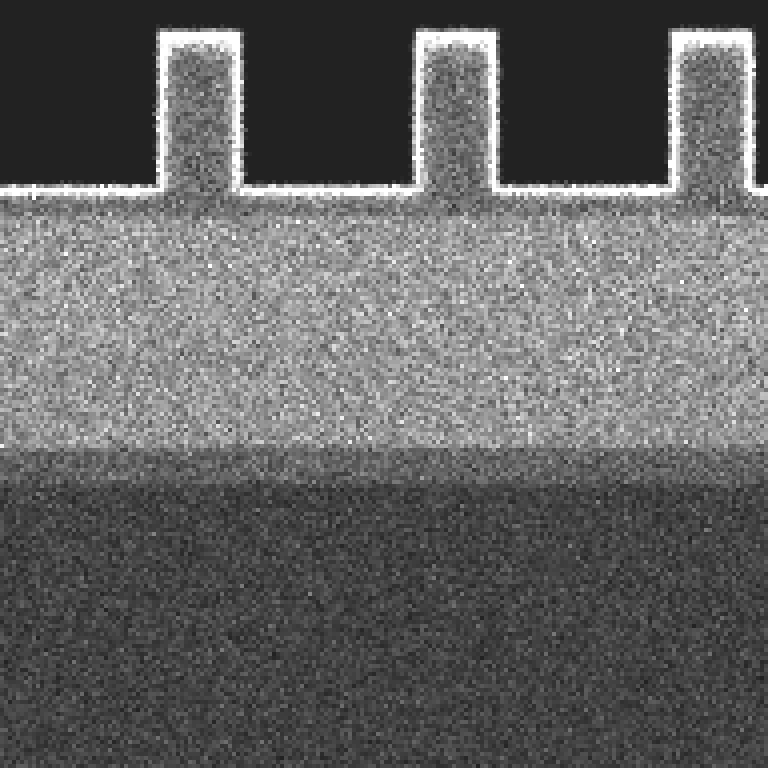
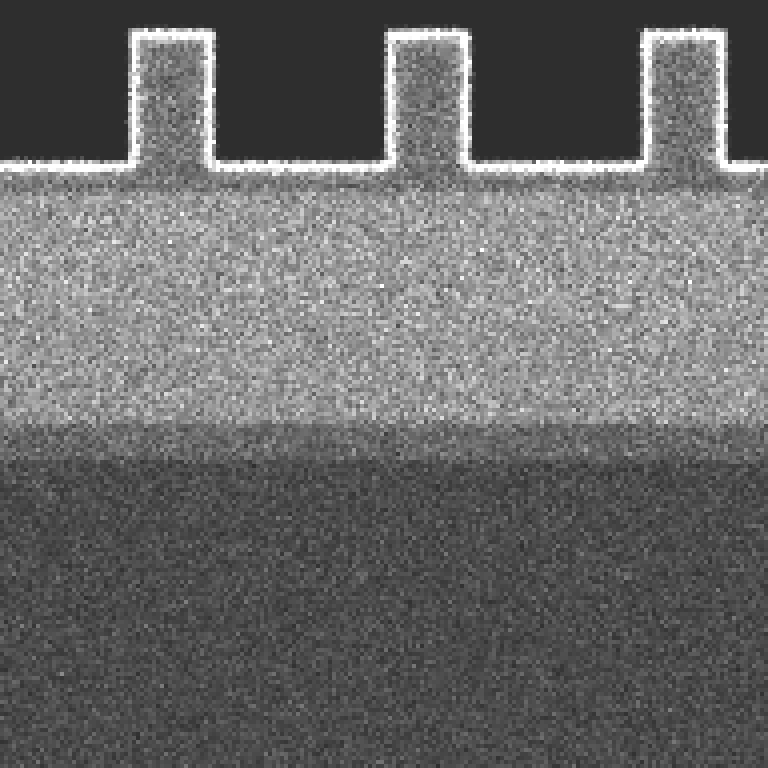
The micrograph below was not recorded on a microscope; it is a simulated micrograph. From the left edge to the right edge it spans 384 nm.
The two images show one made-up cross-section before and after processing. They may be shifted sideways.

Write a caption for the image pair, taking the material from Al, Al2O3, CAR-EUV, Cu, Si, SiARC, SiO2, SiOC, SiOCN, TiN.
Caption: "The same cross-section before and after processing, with SiARC removed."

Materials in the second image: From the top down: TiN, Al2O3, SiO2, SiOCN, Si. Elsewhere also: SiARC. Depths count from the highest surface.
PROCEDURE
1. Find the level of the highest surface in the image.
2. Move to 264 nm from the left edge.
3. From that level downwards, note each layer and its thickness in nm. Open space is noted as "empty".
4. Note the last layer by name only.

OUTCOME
empty 66, TiN 14, Al2O3 64, SiO2 52, SiOCN 18, Si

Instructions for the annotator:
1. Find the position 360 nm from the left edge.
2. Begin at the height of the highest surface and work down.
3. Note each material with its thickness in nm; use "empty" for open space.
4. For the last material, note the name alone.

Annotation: TiN 80, Al2O3 64, SiO2 52, SiOCN 18, Si